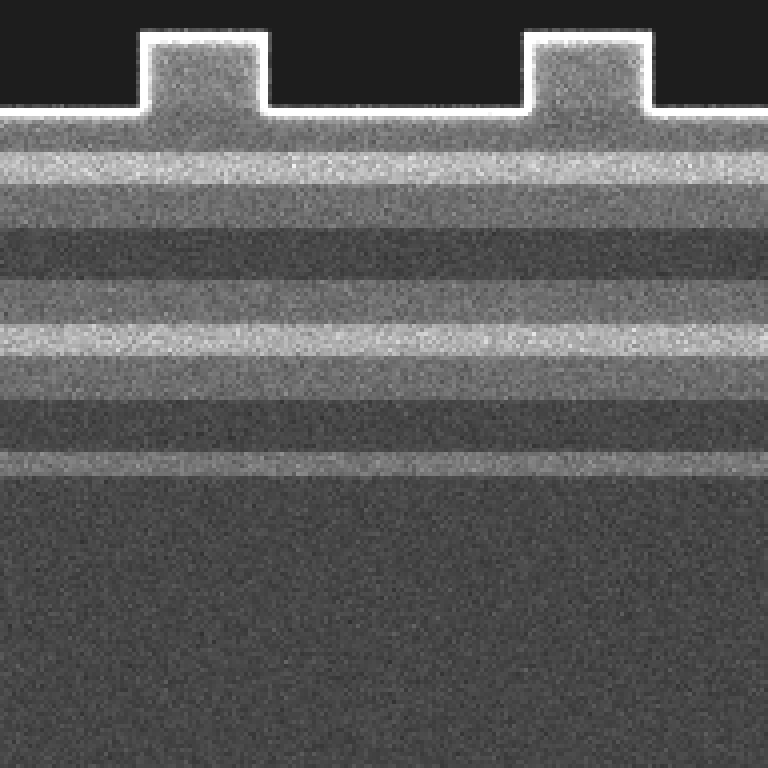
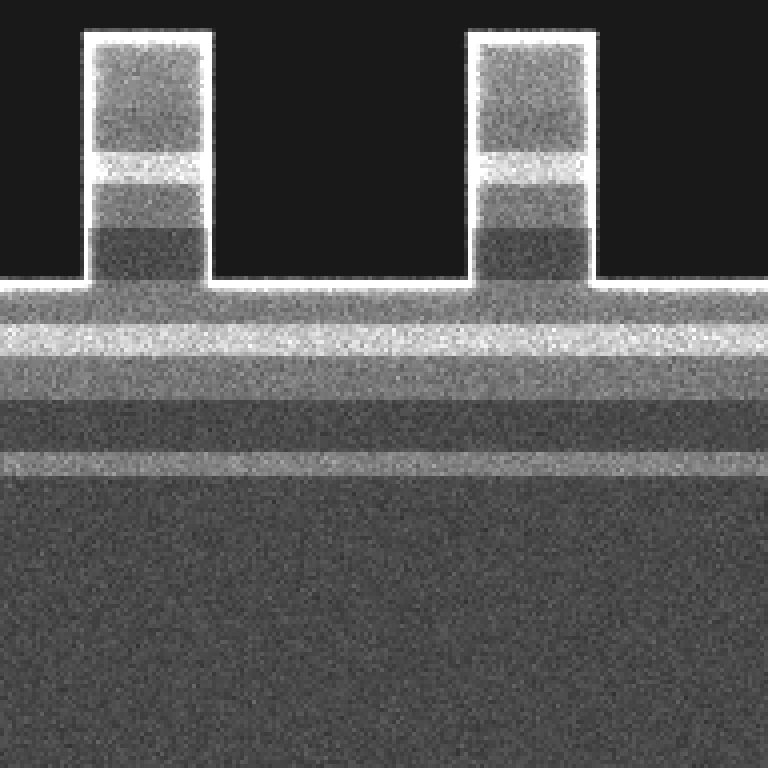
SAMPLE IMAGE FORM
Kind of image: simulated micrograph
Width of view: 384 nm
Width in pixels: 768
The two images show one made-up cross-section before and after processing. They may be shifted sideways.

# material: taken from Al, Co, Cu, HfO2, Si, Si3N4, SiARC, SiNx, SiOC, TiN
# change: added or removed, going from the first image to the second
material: Co and Si and SiNx
change: removed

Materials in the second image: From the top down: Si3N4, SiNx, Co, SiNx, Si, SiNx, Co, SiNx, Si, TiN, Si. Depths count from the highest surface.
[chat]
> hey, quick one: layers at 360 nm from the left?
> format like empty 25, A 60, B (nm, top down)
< empty 124, SiNx 22, Co 16, SiNx 22, Si 26, TiN 12, Si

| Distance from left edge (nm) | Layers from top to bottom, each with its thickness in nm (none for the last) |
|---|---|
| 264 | Si3N4 38, SiNx 22, Co 16, SiNx 22, Si 26, SiNx 22, Co 16, SiNx 22, Si 26, TiN 12, Si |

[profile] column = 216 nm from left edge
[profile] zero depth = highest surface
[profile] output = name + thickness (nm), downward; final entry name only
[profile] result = empty 124, SiNx 22, Co 16, SiNx 22, Si 26, TiN 12, Si